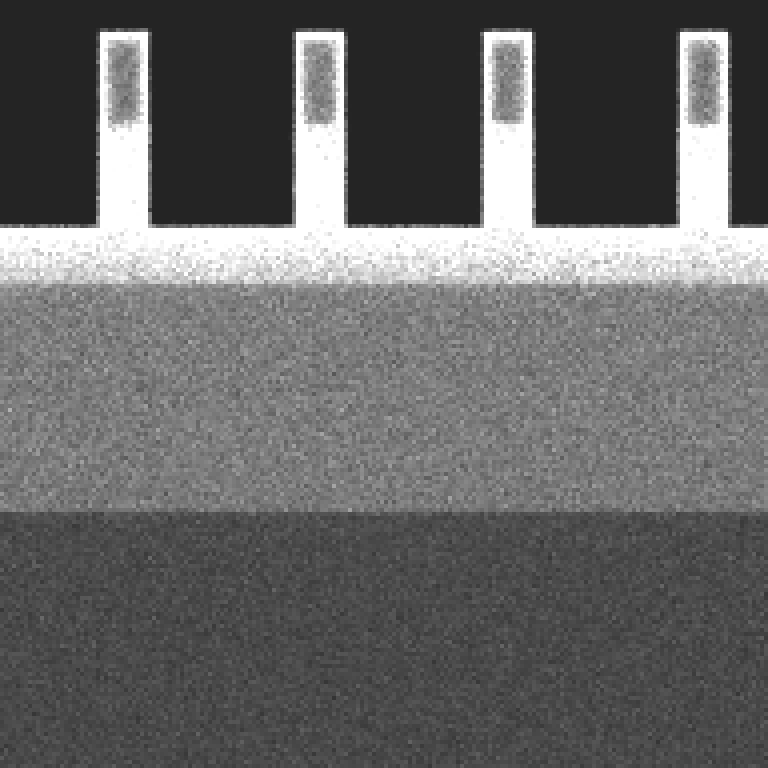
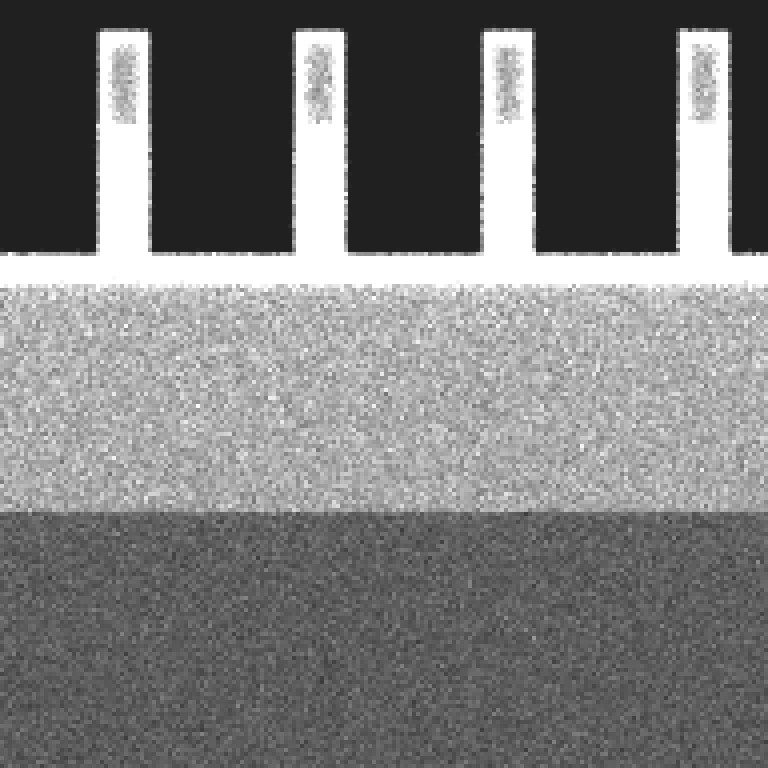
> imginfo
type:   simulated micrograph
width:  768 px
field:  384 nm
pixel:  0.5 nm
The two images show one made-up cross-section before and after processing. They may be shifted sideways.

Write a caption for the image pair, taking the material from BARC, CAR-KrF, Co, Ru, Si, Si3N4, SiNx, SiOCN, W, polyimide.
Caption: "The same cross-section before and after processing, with Ru removed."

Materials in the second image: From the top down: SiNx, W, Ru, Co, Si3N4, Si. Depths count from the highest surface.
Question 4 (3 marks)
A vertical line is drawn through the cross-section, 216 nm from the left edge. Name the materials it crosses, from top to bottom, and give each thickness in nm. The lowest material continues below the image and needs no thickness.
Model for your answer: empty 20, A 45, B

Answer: empty 112, Co 14, Si3N4 114, Si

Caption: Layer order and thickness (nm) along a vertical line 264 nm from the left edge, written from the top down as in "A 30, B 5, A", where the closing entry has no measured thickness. SiNx 46, W 52, Ru 14, Co 14, Si3N4 114, Si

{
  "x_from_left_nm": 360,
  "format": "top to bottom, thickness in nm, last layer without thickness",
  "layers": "SiNx 46, W 52, Ru 14, Co 14, Si3N4 114, Si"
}